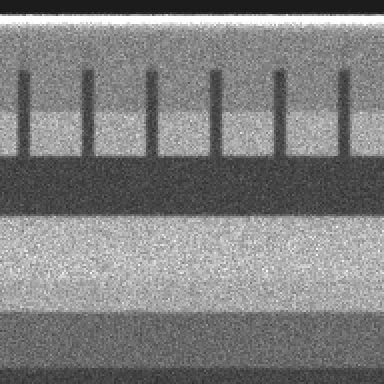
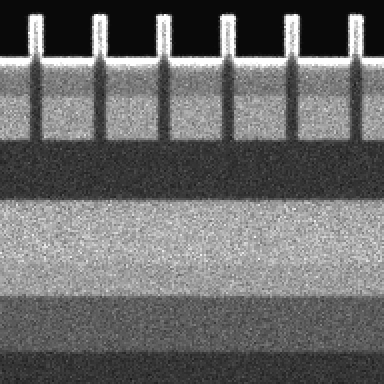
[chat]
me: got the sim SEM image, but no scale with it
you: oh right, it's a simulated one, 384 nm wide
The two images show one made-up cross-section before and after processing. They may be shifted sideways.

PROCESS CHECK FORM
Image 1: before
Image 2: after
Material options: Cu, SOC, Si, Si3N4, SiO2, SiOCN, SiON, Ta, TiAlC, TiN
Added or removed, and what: removed, SOC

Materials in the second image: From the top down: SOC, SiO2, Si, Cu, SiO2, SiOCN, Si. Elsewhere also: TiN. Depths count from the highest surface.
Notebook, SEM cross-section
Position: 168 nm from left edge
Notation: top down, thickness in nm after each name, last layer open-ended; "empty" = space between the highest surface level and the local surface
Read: TiN 38, Si 146, Cu 64, SiO2 32, SiOCN 56, Si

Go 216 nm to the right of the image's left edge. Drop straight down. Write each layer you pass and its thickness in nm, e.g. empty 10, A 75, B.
empty 42, SOC 38, SiO2 44, Si 60, Cu 64, SiO2 32, SiOCN 56, Si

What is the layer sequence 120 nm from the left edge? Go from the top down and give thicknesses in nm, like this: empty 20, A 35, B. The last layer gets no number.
empty 42, SOC 38, SiO2 44, Si 60, Cu 64, SiO2 32, SiOCN 56, Si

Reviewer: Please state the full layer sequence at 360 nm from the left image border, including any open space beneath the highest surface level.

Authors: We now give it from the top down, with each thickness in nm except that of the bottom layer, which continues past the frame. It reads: TiN 38, Si 146, Cu 64, SiO2 32, SiOCN 56, Si